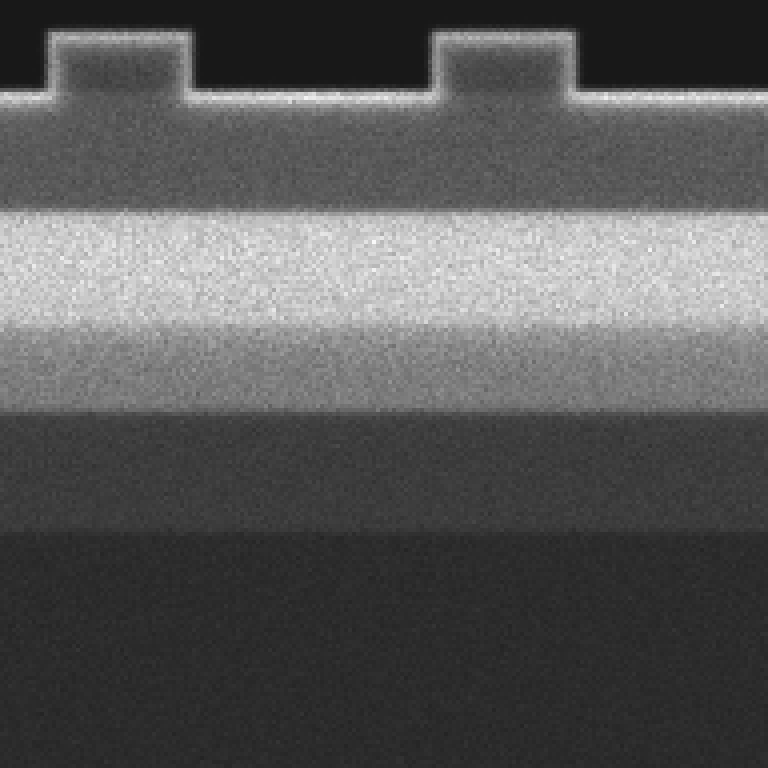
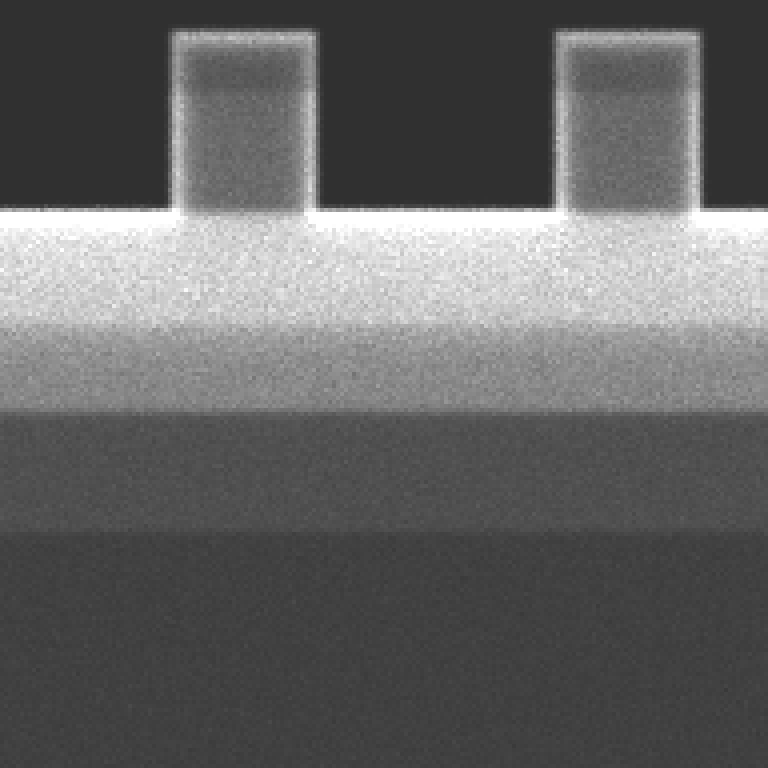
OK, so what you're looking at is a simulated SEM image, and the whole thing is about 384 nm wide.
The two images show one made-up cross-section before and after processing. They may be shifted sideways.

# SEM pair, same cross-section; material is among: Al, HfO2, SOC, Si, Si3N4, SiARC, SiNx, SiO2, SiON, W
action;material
removed;SiO2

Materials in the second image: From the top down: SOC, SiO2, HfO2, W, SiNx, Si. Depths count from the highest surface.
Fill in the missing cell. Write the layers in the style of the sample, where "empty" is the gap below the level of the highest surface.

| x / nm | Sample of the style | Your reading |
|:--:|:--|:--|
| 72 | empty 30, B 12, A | empty 90, HfO2 56, W 44, SiNx 60, Si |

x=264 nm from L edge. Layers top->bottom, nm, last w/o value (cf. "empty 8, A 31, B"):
empty 90, HfO2 56, W 44, SiNx 60, Si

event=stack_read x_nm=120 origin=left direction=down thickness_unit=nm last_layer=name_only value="SOC 30, SiO2 60, HfO2 56, W 44, SiNx 60, Si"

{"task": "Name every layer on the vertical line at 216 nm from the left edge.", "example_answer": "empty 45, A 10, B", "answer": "empty 90, HfO2 56, W 44, SiNx 60, Si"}